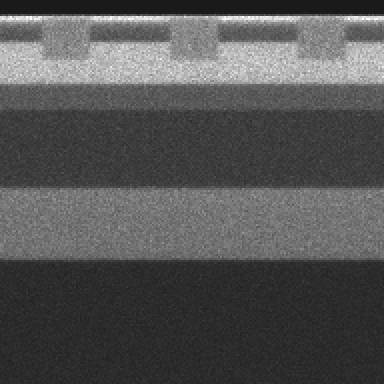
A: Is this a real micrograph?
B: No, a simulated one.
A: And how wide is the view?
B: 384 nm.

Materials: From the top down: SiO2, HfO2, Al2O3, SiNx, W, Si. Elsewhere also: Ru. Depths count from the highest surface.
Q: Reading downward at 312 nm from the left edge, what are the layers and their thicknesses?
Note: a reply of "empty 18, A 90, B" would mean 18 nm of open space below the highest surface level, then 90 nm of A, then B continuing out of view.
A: Ru 44, HfO2 24, Al2O3 26, SiNx 78, W 72, Si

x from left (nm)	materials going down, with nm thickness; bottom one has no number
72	Ru 44, HfO2 24, Al2O3 26, SiNx 78, W 72, Si